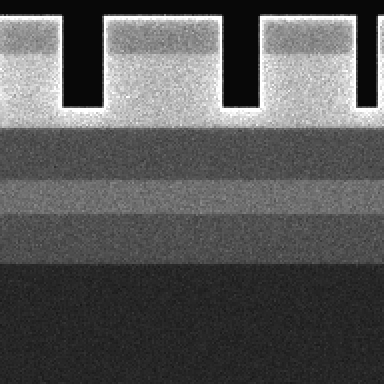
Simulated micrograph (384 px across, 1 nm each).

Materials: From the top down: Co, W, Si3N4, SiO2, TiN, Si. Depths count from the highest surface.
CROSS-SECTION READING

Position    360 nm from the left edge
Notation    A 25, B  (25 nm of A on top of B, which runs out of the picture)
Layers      empty 92, W 20, Si3N4 52, SiO2 34, TiN 50, Si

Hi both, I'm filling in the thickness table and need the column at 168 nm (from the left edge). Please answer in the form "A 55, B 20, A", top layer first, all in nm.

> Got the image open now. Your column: Co 38, W 74, Si3N4 52, SiO2 34, TiN 50, Si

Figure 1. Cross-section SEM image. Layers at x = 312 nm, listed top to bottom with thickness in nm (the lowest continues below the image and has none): Co 38, W 74, Si3N4 52, SiO2 34, TiN 50, Si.